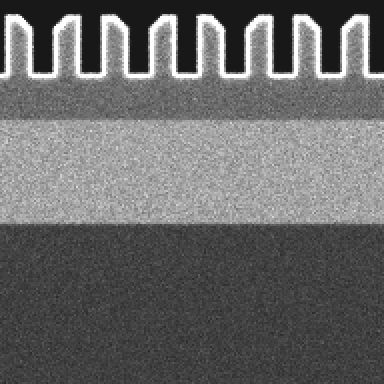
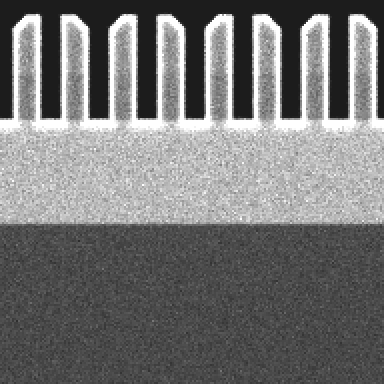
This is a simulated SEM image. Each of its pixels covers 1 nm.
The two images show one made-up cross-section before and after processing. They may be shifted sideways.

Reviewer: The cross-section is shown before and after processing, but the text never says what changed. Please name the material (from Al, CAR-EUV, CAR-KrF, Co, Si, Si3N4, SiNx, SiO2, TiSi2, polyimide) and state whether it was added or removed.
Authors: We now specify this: SiNx, removed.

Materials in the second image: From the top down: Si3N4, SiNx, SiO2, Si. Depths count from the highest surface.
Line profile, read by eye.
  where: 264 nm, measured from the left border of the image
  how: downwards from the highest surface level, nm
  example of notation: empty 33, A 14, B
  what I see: Si3N4 58, SiNx 46, SiO2 104, Si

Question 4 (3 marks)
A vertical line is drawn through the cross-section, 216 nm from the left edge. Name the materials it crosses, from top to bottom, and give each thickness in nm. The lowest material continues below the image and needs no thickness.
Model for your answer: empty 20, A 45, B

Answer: empty 2, Si3N4 56, SiNx 46, SiO2 104, Si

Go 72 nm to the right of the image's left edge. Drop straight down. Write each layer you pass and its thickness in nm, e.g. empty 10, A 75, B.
Si3N4 58, SiNx 46, SiO2 104, Si